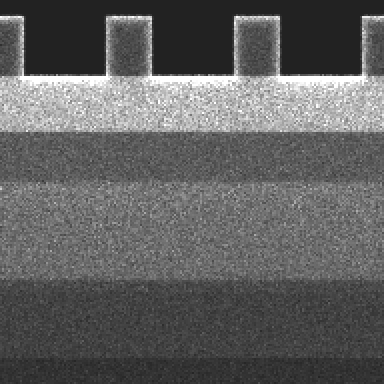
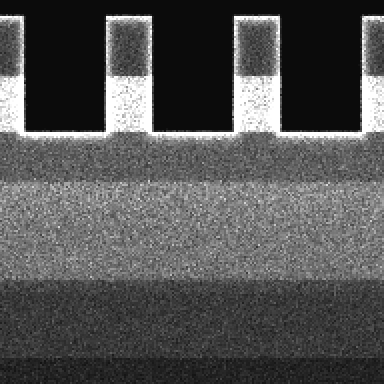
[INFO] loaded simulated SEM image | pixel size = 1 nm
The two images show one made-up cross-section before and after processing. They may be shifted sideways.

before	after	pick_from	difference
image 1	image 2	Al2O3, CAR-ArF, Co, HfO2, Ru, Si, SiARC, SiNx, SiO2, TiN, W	HfO2 removed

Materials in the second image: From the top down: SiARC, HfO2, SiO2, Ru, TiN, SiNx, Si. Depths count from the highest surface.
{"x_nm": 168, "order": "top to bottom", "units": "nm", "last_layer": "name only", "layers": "empty 116, SiO2 50, Ru 98, TiN 12, SiNx 66, Si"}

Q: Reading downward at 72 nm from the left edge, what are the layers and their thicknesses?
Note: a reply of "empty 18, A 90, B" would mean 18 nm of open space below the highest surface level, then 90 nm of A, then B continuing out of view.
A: empty 116, SiO2 50, Ru 98, TiN 12, SiNx 66, Si